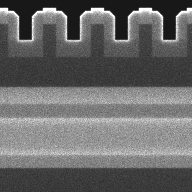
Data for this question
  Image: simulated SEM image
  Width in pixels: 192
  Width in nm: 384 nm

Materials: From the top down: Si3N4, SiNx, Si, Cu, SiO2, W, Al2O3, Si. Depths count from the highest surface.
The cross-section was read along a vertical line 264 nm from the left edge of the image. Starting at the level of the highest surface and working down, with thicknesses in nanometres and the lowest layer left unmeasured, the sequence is empty 8, Si3N4 56, SiNx 34, Si 60, Cu 34, SiO2 28, W 74, Al2O3 26, Si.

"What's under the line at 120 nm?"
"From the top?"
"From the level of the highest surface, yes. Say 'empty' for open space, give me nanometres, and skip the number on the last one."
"empty 6, Si3N4 58, SiNx 34, Si 60, Cu 34, SiO2 28, W 74, Al2O3 26, Si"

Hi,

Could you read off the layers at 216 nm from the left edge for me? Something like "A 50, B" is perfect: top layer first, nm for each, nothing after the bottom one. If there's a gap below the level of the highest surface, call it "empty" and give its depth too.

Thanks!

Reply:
empty 6, Si3N4 58, SiNx 34, Si 60, Cu 34, SiO2 28, W 74, Al2O3 26, Si